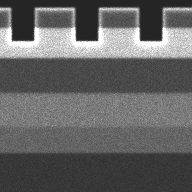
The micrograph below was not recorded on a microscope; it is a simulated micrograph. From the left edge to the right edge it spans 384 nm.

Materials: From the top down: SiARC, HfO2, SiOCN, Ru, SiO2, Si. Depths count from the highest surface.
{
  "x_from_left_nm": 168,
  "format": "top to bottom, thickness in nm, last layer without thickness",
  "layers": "empty 68, HfO2 32, SiOCN 70, Ru 68, SiO2 52, Si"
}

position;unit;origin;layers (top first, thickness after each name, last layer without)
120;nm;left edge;SiARC 40, HfO2 60, SiOCN 70, Ru 68, SiO2 52, Si